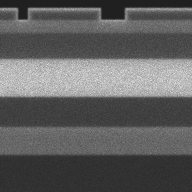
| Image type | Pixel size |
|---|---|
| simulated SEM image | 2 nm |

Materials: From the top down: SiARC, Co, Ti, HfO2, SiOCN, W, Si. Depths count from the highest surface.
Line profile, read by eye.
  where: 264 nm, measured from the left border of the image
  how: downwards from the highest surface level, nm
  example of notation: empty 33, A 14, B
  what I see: SiARC 24, Co 26, Ti 52, HfO2 76, SiOCN 60, W 56, Si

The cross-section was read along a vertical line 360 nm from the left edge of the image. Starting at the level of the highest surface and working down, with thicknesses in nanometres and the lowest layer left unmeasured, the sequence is SiARC 24, Co 26, Ti 52, HfO2 76, SiOCN 60, W 56, Si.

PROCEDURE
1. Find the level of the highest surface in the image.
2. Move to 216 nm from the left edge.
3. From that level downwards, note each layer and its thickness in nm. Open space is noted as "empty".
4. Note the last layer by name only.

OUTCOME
empty 24, Co 26, Ti 52, HfO2 76, SiOCN 60, W 56, Si